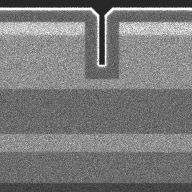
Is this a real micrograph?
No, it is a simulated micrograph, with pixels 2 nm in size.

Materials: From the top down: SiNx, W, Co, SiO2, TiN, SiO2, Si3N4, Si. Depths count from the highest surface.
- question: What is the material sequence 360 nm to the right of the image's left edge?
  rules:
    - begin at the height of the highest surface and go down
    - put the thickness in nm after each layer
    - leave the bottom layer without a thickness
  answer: SiNx 28, W 26, Co 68, SiO2 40, TiN 90, SiO2 36, Si3N4 62, Si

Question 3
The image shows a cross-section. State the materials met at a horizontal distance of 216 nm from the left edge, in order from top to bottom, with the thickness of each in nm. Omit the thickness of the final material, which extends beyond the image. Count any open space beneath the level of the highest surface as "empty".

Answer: empty 8, SiNx 134, SiO2 20, TiN 90, SiO2 36, Si3N4 62, Si